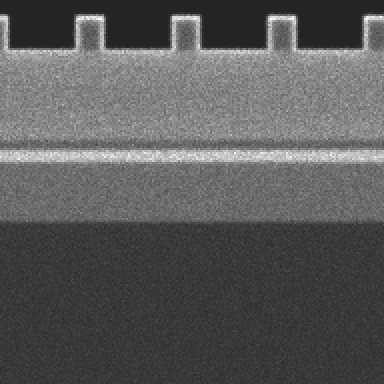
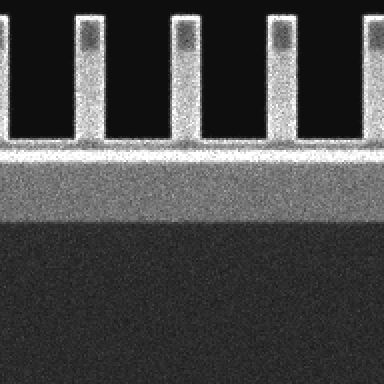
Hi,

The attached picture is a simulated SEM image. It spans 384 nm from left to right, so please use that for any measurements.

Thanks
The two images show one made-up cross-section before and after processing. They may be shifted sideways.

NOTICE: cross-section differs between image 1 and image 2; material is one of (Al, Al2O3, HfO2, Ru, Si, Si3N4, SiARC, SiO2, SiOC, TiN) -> removed: Ru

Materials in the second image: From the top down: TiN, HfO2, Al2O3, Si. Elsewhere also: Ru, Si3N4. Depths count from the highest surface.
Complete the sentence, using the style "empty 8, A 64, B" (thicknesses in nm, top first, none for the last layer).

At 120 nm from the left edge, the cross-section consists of empty 124, TiN 10, HfO2 12, Al2O3 60, Si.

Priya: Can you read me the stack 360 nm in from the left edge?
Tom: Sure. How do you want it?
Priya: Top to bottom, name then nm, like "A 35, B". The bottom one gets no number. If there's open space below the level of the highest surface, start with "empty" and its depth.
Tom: empty 124, TiN 10, HfO2 12, Al2O3 60, Si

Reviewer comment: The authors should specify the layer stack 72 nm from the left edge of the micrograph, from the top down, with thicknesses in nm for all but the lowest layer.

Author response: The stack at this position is empty 124, TiN 10, HfO2 12, Al2O3 60, Si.